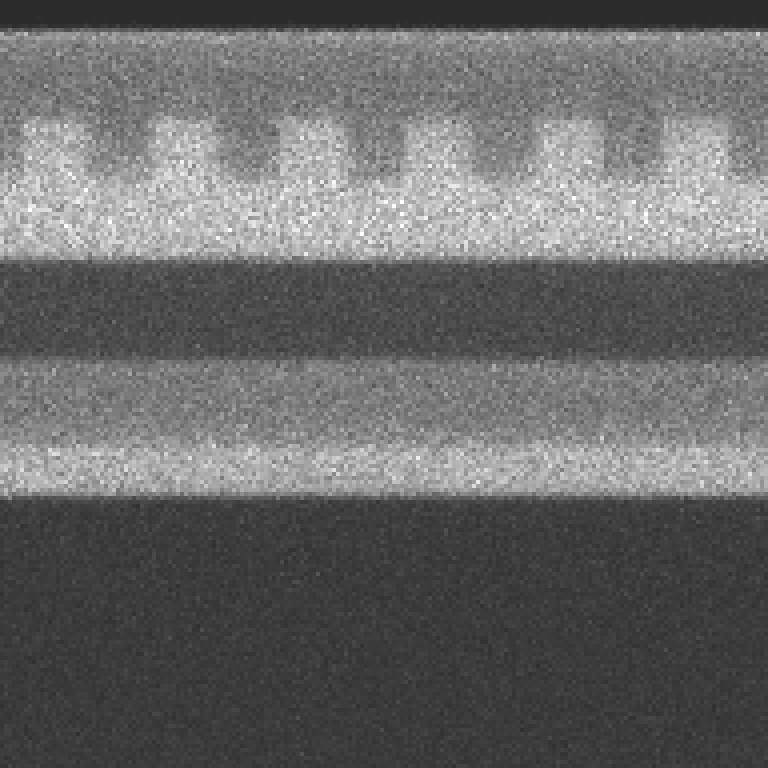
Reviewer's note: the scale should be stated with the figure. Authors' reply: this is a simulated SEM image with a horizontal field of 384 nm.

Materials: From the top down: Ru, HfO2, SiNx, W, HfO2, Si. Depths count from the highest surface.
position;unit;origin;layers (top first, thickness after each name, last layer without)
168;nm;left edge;Ru 44, HfO2 70, SiNx 50, W 44, HfO2 24, Si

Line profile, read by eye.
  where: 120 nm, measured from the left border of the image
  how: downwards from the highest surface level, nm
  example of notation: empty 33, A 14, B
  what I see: Ru 74, HfO2 40, SiNx 50, W 44, HfO2 24, Si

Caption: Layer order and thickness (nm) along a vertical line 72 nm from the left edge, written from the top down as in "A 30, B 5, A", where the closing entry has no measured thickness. Ru 74, HfO2 40, SiNx 50, W 44, HfO2 24, Si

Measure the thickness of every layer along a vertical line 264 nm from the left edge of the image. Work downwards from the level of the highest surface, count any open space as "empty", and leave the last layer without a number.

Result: Ru 74, HfO2 40, SiNx 50, W 44, HfO2 24, Si